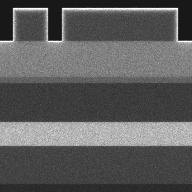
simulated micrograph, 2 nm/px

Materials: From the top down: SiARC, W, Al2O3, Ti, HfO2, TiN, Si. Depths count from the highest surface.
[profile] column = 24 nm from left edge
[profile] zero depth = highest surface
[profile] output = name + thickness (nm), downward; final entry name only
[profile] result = empty 66, W 72, Al2O3 12, Ti 78, HfO2 48, TiN 76, Si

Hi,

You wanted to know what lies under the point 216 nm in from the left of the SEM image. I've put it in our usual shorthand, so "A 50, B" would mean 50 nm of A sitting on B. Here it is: SiARC 66, W 72, Al2O3 12, Ti 78, HfO2 48, TiN 76, Si